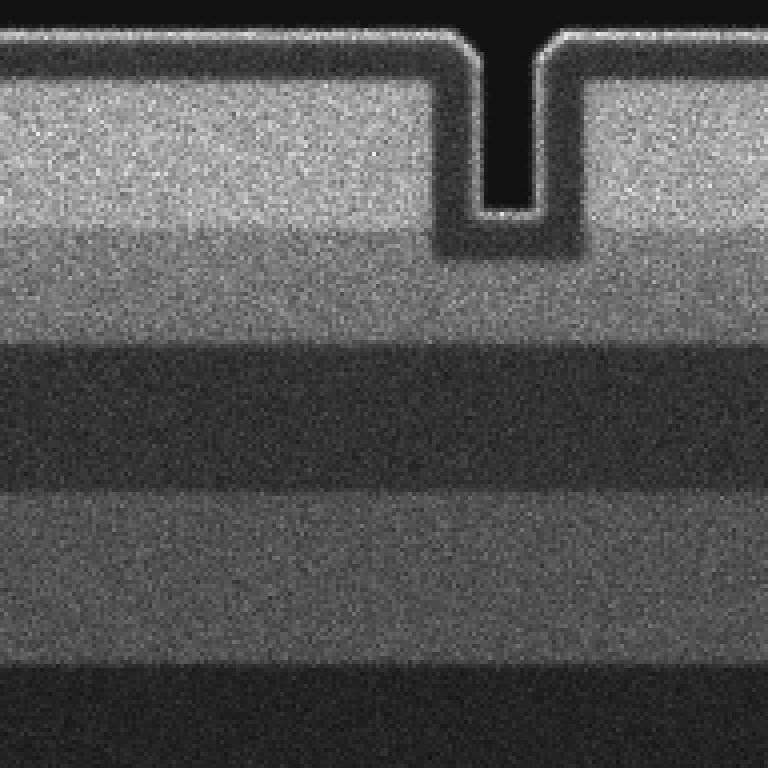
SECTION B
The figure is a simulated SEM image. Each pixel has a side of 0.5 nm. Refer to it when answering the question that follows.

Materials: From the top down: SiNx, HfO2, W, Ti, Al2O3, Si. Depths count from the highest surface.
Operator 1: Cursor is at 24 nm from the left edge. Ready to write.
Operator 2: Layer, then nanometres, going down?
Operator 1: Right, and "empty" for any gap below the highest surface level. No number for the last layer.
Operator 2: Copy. SiNx 24, HfO2 74, W 58, Ti 74, Al2O3 86, Si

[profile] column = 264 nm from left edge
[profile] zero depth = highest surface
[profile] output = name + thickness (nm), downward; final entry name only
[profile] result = empty 90, SiNx 24, W 42, Ti 74, Al2O3 86, Si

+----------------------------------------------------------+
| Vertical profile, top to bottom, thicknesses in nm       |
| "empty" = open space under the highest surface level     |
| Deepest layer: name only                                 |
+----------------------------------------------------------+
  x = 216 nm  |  SiNx 114, W 42, Ti 74, Al2O3 86, Si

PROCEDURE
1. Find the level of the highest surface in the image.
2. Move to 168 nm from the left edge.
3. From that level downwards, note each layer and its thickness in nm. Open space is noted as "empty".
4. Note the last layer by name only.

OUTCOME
SiNx 24, HfO2 74, W 58, Ti 74, Al2O3 86, Si